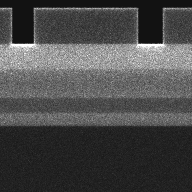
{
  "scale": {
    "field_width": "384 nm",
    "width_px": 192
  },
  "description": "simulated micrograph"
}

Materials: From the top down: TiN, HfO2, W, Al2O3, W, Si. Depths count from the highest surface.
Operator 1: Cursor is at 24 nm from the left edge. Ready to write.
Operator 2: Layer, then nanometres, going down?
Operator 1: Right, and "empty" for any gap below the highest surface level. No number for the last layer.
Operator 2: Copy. empty 72, HfO2 50, W 58, Al2O3 30, W 26, Si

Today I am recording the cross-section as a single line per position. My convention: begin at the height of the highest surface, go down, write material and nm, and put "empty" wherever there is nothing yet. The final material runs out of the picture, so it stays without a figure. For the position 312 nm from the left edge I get empty 72, HfO2 50, W 58, Al2O3 30, W 26, Si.